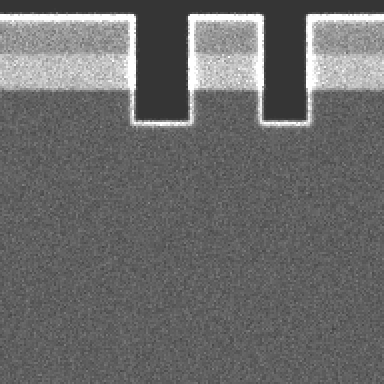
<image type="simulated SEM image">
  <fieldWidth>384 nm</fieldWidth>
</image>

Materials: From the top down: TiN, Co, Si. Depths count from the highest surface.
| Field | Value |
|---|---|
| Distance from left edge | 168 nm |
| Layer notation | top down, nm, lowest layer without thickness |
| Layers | empty 106, Si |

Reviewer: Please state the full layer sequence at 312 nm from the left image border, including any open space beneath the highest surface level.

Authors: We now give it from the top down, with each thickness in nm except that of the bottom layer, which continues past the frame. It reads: TiN 38, Co 36, Si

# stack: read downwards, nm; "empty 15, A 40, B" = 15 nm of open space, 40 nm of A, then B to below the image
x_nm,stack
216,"TiN 38, Co 36, Si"